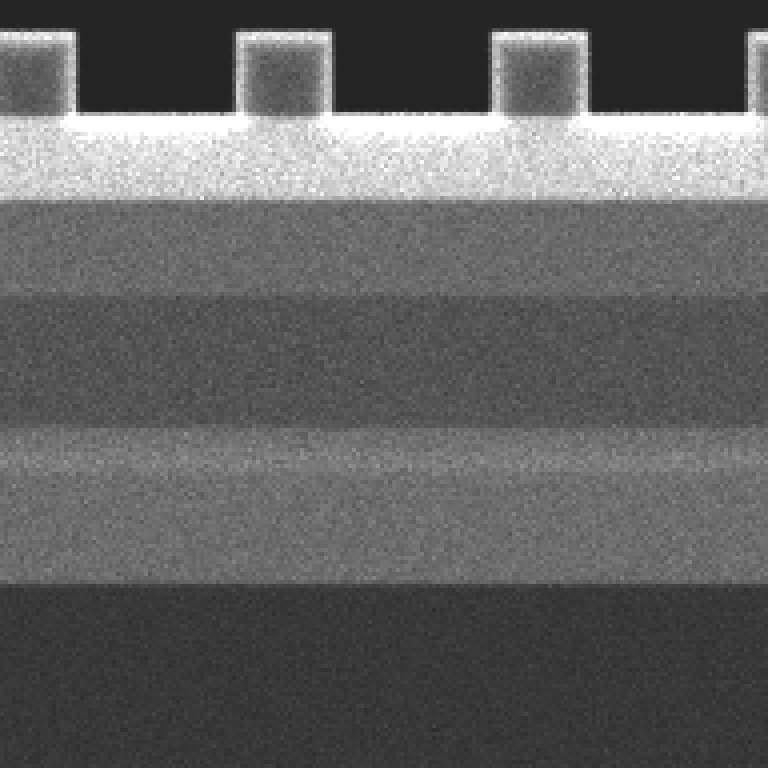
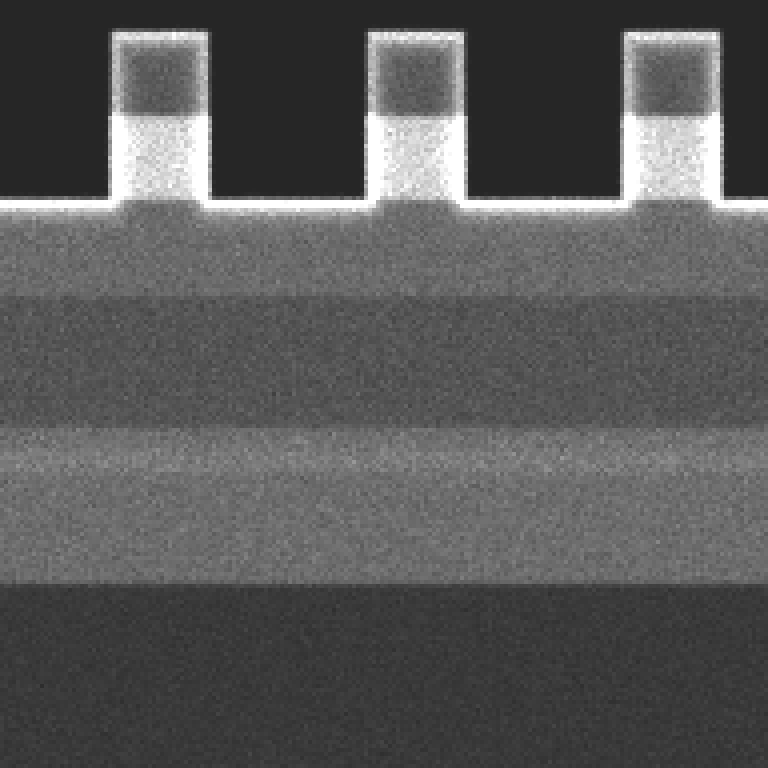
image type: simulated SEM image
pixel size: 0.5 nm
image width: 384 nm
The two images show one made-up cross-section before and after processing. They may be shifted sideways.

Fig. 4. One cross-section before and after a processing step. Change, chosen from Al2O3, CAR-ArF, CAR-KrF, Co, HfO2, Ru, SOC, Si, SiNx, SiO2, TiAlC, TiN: HfO2 removed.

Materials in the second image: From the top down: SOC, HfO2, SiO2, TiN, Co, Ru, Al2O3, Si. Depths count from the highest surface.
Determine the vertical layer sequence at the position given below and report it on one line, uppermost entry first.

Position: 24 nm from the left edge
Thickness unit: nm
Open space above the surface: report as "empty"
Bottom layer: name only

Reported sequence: empty 84, SiO2 48, TiN 66, Co 12, Ru 10, Al2O3 56, Si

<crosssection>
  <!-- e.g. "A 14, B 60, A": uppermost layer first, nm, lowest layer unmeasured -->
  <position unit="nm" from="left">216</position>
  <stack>SOC 42, HfO2 42, SiO2 48, TiN 66, Co 12, Ru 10, Al2O3 56, Si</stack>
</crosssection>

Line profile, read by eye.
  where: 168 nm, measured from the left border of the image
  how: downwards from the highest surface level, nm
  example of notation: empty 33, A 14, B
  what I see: empty 84, SiO2 48, TiN 66, Co 12, Ru 10, Al2O3 56, Si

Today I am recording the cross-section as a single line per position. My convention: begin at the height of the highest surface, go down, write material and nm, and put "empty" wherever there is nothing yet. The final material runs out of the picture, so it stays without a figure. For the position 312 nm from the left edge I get SOC 42, HfO2 42, SiO2 48, TiN 66, Co 12, Ru 10, Al2O3 56, Si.